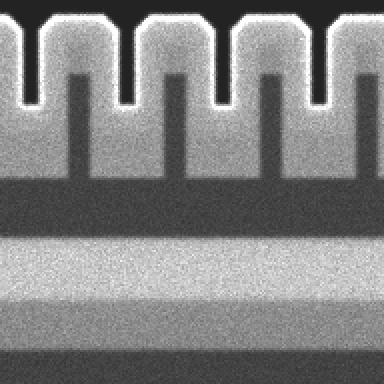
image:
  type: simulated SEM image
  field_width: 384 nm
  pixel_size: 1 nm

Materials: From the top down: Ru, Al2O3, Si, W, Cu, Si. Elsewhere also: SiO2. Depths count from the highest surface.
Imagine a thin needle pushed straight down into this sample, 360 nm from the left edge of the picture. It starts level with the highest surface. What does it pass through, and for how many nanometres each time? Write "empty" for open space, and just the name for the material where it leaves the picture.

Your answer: Ru 28, SiO2 30, Si 164, W 62, Cu 50, Si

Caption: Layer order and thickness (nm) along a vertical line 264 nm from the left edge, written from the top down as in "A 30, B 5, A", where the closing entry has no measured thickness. Ru 28, SiO2 30, Si 164, W 62, Cu 50, Si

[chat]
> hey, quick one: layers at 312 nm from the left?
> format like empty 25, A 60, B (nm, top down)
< empty 90, Ru 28, Al2O3 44, Si 60, W 62, Cu 50, Si